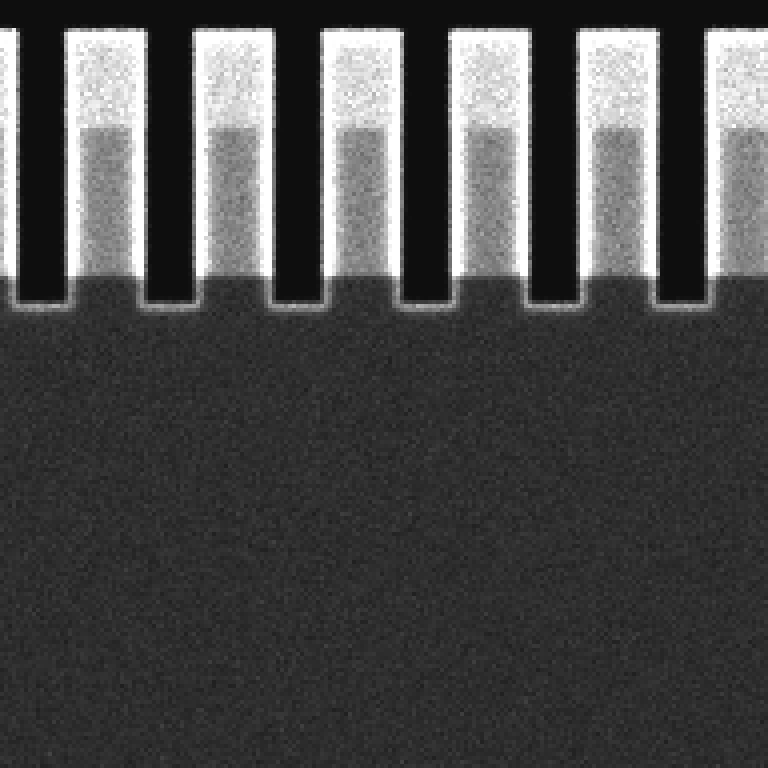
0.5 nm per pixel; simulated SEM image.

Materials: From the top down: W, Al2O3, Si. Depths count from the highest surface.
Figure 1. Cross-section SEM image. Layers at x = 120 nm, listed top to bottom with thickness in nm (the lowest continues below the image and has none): W 48, Al2O3 74, Si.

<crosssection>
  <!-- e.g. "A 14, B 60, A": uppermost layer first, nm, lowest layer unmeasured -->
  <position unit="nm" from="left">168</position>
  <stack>W 48, Al2O3 74, Si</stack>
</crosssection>